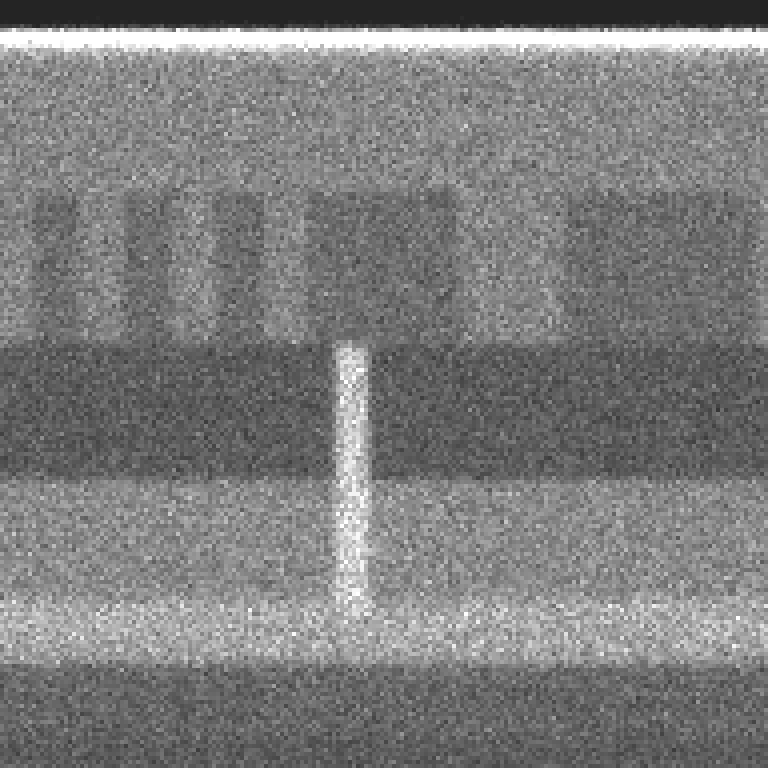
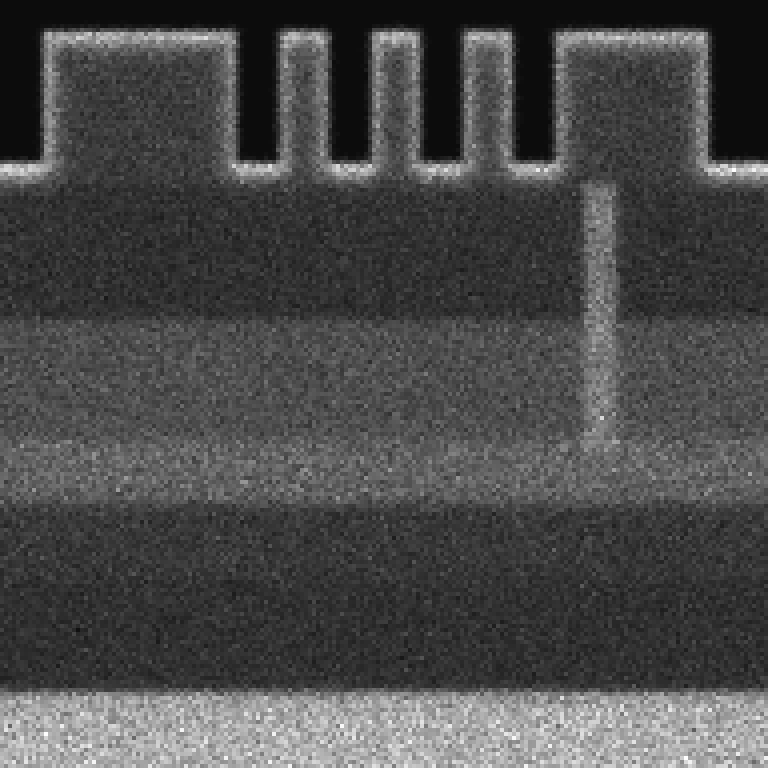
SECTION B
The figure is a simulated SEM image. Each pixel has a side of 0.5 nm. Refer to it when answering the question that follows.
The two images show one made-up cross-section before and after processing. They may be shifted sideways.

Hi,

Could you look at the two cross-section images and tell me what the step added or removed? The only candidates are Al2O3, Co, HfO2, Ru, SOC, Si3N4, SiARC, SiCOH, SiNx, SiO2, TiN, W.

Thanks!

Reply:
removed SiO2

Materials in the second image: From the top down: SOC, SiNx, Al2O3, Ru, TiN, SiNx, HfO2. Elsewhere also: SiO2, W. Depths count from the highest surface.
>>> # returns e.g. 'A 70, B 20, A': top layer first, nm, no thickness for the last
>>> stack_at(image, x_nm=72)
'SOC 76, SiNx 68, Al2O3 60, Ru 32, TiN 38, SiNx 56, HfO2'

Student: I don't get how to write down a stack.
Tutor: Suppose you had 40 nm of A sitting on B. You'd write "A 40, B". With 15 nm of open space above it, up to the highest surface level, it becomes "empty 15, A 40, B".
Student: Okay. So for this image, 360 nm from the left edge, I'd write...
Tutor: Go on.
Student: empty 66, SiO2 10, SiNx 68, Al2O3 60, Ru 32, TiN 38, SiNx 56, HfO2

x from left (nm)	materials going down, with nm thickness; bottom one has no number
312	SOC 76, SiNx 68, Al2O3 60, Ru 32, TiN 38, SiNx 56, HfO2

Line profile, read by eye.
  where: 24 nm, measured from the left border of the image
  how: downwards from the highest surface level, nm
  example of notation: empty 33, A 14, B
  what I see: SOC 76, SiNx 68, Al2O3 60, Ru 32, TiN 38, SiNx 56, HfO2